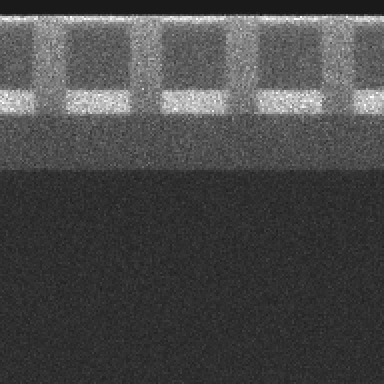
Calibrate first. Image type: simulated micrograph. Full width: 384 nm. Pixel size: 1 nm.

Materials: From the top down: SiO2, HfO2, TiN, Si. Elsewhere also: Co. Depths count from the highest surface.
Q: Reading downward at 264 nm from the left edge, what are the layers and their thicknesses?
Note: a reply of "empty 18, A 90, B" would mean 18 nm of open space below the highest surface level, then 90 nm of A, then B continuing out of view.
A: SiO2 74, HfO2 24, TiN 56, Si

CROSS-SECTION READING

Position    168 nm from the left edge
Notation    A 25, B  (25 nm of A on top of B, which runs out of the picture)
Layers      SiO2 74, HfO2 24, TiN 56, Si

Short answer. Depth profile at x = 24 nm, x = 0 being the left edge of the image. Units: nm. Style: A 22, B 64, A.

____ SiO2 74, HfO2 24, TiN 56, Si